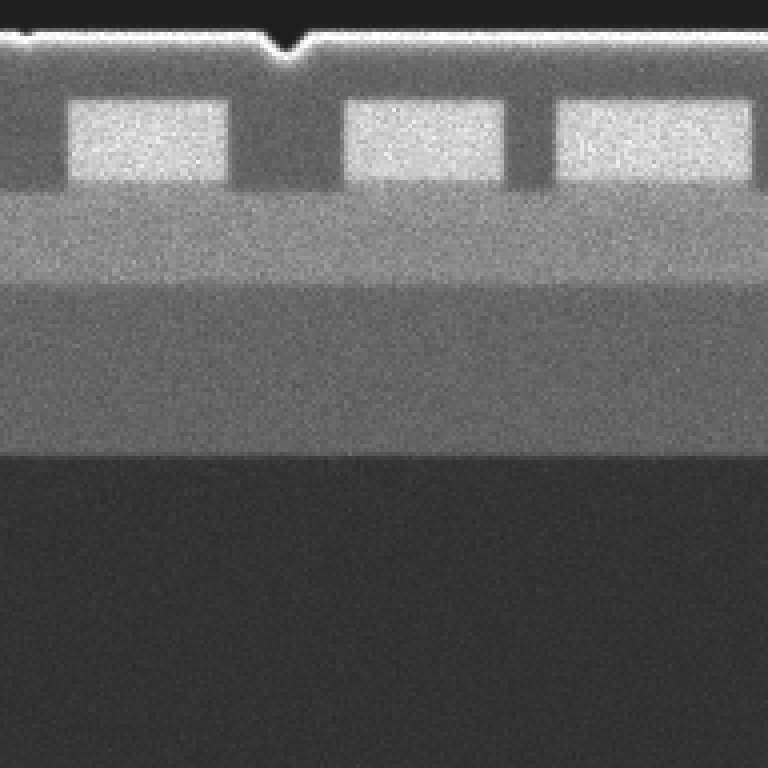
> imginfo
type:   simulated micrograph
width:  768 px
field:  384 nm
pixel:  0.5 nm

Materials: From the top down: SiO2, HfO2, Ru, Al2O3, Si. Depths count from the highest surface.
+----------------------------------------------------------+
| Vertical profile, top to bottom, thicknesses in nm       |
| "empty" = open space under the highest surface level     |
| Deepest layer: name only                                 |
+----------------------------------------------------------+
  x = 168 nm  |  SiO2 80, Ru 46, Al2O3 86, Si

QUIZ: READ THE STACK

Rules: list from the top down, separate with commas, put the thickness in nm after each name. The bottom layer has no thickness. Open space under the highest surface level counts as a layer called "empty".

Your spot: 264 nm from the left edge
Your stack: SiO2 80, Ru 46, Al2O3 86, Si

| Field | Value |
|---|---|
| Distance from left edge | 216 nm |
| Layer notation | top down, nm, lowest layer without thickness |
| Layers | SiO2 34, HfO2 40, Ru 52, Al2O3 86, Si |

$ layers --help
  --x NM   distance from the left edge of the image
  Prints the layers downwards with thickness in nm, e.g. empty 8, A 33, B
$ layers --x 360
SiO2 34, HfO2 40, Ru 52, Al2O3 86, Si